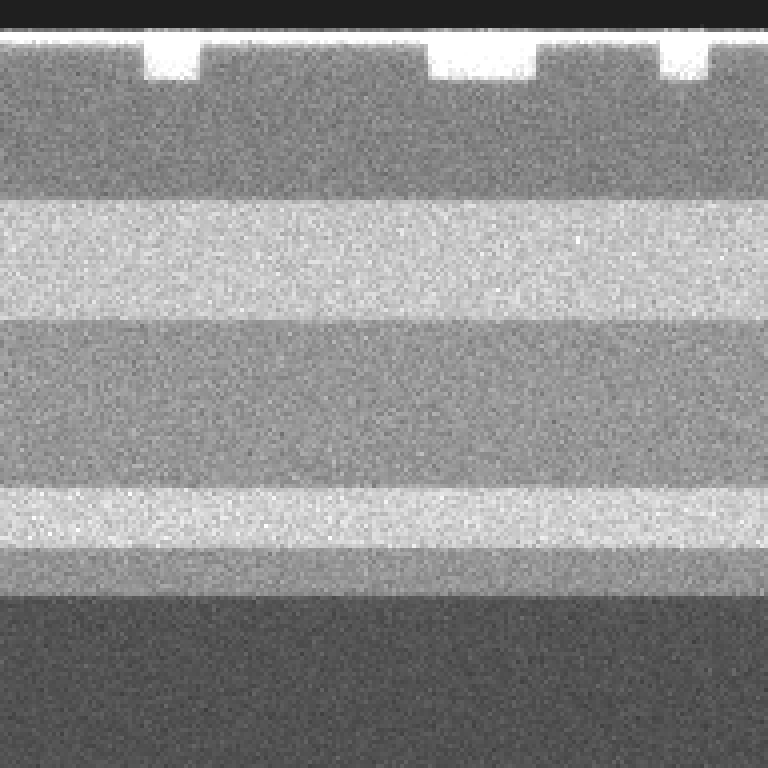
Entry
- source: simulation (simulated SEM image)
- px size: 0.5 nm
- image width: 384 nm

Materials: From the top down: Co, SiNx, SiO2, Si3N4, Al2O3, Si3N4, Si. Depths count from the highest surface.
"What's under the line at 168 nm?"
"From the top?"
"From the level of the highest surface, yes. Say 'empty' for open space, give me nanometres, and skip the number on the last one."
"SiNx 84, SiO2 60, Si3N4 84, Al2O3 30, Si3N4 24, Si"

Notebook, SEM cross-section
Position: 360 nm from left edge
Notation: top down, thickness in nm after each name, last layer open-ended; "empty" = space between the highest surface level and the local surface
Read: SiNx 84, SiO2 60, Si3N4 84, Al2O3 30, Si3N4 24, Si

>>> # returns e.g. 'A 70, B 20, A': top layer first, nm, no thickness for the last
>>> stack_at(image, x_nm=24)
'SiNx 84, SiO2 60, Si3N4 84, Al2O3 30, Si3N4 24, Si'